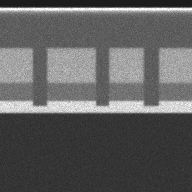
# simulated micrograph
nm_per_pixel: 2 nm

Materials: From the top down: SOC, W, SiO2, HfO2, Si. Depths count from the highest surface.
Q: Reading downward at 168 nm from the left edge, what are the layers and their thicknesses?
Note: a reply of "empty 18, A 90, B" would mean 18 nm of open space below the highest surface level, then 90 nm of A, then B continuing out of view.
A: SOC 80, W 70, SiO2 36, HfO2 24, Si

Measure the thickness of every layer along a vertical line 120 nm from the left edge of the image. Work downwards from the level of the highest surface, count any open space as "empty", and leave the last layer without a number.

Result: SOC 80, W 70, SiO2 36, HfO2 24, Si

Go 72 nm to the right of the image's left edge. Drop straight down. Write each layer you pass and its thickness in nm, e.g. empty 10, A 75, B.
SOC 196, HfO2 14, Si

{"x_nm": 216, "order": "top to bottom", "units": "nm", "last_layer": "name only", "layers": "SOC 196, HfO2 14, Si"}